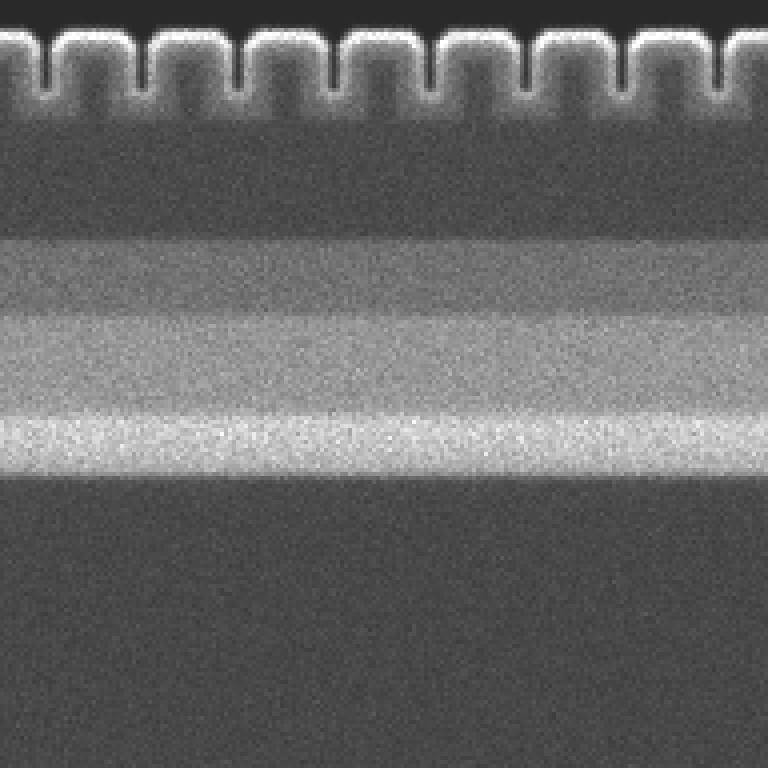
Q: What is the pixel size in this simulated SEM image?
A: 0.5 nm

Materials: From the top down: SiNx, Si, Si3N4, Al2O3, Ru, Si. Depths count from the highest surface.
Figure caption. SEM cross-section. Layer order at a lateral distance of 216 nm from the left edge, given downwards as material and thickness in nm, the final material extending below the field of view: empty 30, SiNx 14, Si 60, Si3N4 38, Al2O3 50, Ru 30, Si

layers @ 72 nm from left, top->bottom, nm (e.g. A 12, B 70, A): empty 30, SiNx 14, Si 60, Si3N4 38, Al2O3 50, Ru 30, Si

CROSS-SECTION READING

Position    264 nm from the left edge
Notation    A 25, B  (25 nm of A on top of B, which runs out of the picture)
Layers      empty 30, SiNx 14, Si 60, Si3N4 38, Al2O3 50, Ru 30, Si